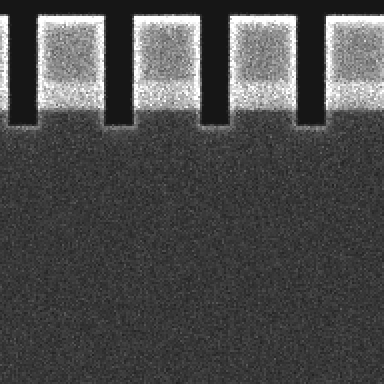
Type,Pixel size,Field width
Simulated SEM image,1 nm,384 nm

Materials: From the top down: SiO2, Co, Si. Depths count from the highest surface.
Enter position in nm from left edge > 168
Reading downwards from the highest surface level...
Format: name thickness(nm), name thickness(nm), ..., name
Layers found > SiO2 66, Co 28, Si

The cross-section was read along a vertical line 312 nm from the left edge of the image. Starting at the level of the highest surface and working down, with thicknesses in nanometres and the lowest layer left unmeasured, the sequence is empty 110, Si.